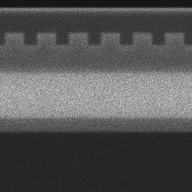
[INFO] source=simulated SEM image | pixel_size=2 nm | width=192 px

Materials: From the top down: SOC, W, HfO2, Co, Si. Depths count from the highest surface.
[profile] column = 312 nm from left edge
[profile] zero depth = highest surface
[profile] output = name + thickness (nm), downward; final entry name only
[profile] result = SOC 74, W 56, HfO2 90, Co 28, Si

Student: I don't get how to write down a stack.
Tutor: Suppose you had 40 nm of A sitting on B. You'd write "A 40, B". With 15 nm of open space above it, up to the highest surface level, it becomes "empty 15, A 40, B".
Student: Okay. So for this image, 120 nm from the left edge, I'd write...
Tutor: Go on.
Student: SOC 74, W 56, HfO2 90, Co 28, Si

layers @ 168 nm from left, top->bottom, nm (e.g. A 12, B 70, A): SOC 50, W 80, HfO2 90, Co 28, Si